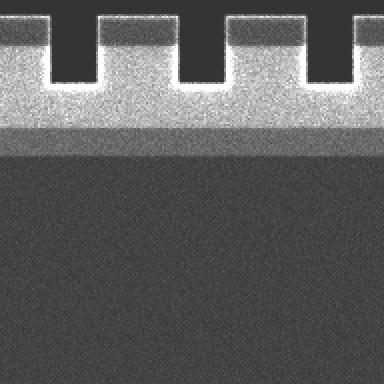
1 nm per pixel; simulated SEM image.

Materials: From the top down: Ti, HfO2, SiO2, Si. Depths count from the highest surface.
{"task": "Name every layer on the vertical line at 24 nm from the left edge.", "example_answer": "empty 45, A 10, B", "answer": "Ti 30, HfO2 82, SiO2 28, Si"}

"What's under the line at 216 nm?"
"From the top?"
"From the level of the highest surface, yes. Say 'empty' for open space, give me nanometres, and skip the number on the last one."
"empty 68, HfO2 44, SiO2 28, Si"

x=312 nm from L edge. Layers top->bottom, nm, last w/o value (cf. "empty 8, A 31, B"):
empty 68, HfO2 44, SiO2 28, Si